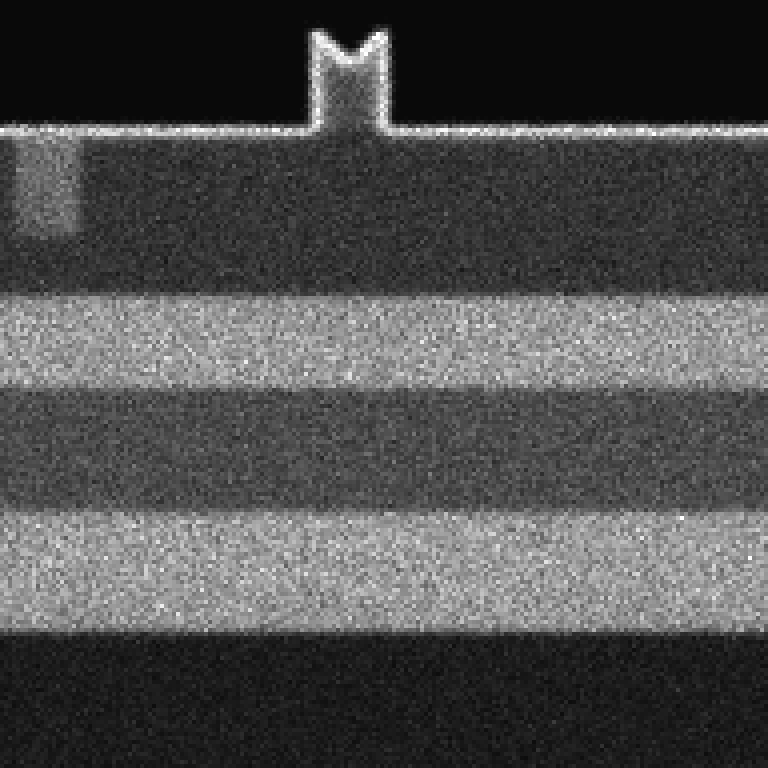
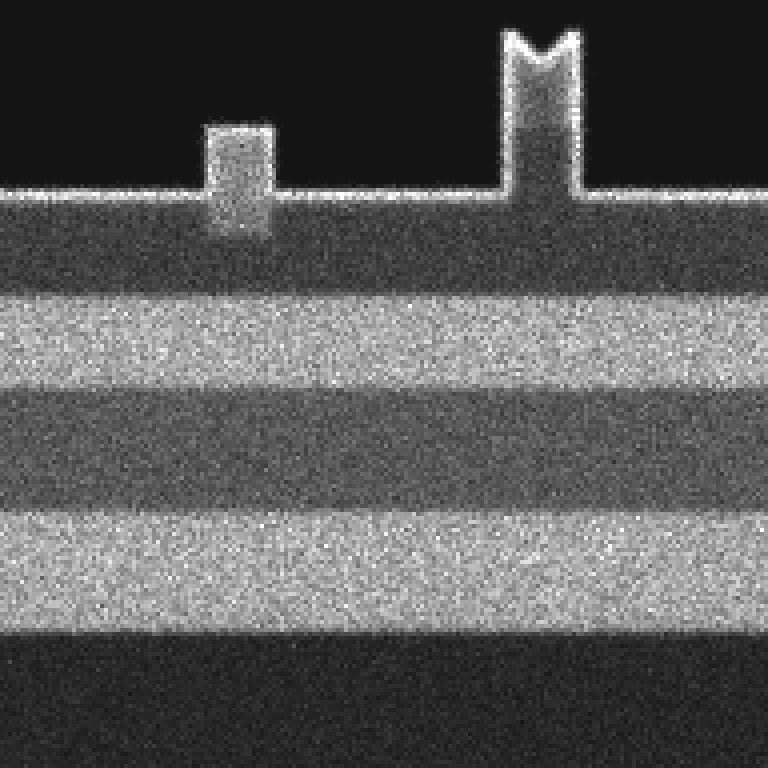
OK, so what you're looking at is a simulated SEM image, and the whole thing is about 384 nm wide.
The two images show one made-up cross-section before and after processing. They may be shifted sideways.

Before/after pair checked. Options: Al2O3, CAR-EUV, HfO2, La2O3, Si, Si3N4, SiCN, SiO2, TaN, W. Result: removed Si3N4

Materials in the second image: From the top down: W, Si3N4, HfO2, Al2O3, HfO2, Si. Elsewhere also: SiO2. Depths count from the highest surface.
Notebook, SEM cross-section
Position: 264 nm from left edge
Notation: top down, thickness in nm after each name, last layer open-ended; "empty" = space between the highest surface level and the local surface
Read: empty 8, SiO2 40, Si3N4 84, HfO2 46, Al2O3 62, HfO2 60, Si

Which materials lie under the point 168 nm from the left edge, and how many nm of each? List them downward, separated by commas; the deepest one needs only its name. empty 80, Si3N4 52, HfO2 46, Al2O3 62, HfO2 60, Si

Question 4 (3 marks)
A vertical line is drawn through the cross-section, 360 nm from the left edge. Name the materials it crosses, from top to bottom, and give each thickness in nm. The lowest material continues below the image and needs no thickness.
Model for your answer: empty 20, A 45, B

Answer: empty 80, Si3N4 52, HfO2 46, Al2O3 62, HfO2 60, Si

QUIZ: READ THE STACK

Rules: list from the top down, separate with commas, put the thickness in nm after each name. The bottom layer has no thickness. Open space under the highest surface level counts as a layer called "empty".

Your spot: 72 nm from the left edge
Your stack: empty 80, Si3N4 52, HfO2 46, Al2O3 62, HfO2 60, Si